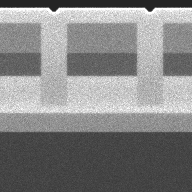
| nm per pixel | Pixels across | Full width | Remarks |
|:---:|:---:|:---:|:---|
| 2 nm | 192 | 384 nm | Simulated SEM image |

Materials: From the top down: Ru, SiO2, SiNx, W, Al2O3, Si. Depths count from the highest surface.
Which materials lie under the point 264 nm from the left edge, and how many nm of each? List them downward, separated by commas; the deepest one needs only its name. Ru 30, SiO2 60, SiNx 46, W 74, Al2O3 38, Si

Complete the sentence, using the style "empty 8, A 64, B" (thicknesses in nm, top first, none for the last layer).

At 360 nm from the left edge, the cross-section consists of Ru 30, SiO2 60, SiNx 46, W 74, Al2O3 38, Si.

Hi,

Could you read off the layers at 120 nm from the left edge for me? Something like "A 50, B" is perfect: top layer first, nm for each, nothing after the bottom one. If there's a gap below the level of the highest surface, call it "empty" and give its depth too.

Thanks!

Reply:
Ru 196, W 14, Al2O3 38, Si